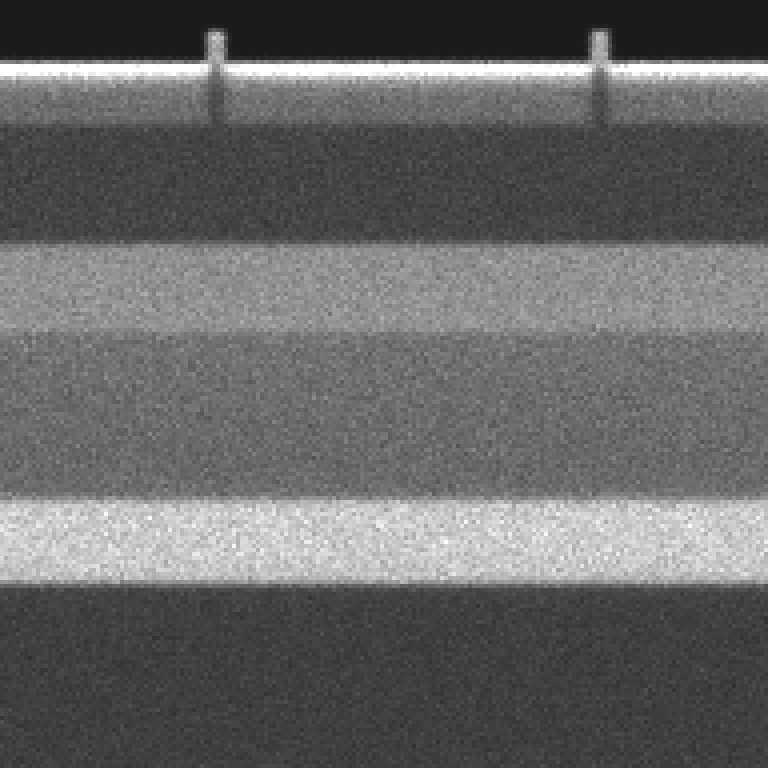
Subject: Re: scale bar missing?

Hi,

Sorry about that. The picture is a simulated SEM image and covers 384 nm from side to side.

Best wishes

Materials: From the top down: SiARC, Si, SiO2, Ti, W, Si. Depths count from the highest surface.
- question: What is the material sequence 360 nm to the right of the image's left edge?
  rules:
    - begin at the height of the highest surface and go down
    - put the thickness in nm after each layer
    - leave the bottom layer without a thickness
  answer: empty 16, SiARC 30, Si 60, SiO2 44, Ti 84, W 42, Si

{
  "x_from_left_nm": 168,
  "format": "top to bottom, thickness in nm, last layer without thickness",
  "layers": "empty 16, SiARC 30, Si 60, SiO2 44, Ti 84, W 42, Si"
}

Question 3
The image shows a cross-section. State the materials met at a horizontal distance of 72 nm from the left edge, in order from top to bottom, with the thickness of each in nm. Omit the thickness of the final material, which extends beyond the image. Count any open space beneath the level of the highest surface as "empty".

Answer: empty 16, SiARC 30, Si 60, SiO2 44, Ti 84, W 42, Si